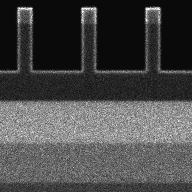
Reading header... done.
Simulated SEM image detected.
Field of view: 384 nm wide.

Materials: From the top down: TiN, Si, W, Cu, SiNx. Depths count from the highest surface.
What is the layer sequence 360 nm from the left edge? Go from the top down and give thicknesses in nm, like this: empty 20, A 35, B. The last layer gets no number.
empty 126, Si 60, W 84, Cu 80, SiNx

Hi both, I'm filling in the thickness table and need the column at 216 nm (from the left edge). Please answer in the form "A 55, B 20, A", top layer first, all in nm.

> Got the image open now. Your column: empty 126, Si 60, W 84, Cu 80, SiNx